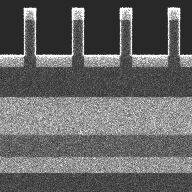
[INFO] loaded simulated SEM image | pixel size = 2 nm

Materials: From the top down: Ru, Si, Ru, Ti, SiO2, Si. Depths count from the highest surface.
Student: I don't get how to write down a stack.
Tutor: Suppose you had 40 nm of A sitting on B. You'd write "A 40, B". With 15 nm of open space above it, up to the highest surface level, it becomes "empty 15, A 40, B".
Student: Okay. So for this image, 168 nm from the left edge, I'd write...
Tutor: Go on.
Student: empty 94, Ru 24, Si 60, Ru 76, Ti 44, SiO2 32, Si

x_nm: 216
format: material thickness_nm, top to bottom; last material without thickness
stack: empty 94, Ru 24, Si 60, Ru 76, Ti 44, SiO2 32, Si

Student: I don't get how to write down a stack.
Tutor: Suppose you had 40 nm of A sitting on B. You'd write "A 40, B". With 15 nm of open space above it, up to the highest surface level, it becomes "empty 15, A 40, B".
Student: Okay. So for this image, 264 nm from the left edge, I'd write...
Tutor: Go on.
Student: empty 94, Ru 24, Si 60, Ru 76, Ti 44, SiO2 32, Si